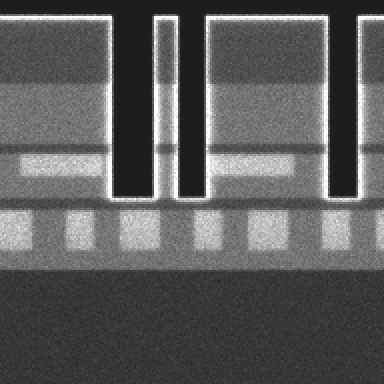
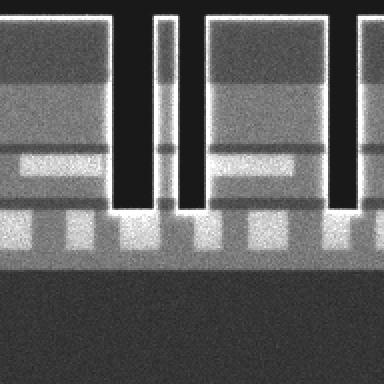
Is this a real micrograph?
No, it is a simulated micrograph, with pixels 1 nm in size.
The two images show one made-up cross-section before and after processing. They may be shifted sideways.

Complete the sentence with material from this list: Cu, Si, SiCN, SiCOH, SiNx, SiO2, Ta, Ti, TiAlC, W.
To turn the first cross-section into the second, SiCN must be removed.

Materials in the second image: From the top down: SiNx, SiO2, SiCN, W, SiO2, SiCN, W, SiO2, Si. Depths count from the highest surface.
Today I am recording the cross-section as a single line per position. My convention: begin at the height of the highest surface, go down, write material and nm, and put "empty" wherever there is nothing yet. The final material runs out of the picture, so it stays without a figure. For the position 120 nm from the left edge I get empty 194, W 40, SiO2 20, Si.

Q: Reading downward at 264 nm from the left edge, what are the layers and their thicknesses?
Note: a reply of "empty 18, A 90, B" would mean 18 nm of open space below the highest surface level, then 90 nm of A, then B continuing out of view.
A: SiNx 68, SiO2 60, SiCN 10, W 22, SiO2 22, SiCN 12, W 40, SiO2 20, Si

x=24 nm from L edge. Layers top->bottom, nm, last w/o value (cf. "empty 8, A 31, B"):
SiNx 68, SiO2 60, SiCN 10, W 22, SiO2 22, SiCN 12, W 40, SiO2 20, Si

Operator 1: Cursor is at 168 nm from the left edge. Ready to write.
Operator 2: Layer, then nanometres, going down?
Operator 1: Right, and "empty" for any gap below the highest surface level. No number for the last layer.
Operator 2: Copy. SiNx 68, SiO2 60, SiCN 10, SiO2 44, SiCN 12, SiO2 60, Si